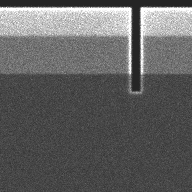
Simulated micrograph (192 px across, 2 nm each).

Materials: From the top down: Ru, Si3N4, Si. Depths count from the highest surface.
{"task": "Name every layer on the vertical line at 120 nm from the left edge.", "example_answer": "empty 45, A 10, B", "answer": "Ru 56, Si3N4 76, Si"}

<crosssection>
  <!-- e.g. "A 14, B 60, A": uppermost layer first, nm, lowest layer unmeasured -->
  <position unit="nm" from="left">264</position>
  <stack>empty 168, Si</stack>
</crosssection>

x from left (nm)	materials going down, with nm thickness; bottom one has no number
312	Ru 56, Si3N4 76, Si